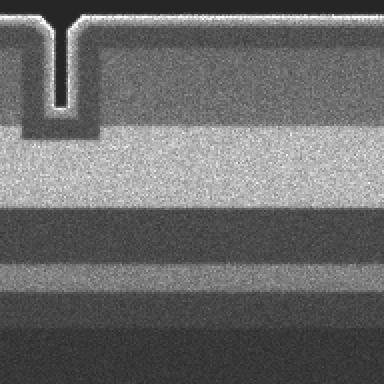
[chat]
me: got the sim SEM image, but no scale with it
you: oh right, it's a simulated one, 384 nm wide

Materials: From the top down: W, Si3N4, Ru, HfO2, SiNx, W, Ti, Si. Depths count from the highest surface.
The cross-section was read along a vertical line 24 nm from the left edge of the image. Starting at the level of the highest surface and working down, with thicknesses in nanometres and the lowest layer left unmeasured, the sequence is W 10, Si3N4 114, HfO2 68, SiNx 56, W 28, Ti 36, Si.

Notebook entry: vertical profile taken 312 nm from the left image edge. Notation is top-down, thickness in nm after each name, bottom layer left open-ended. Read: W 10, Si3N4 22, Ru 78, HfO2 82, SiNx 56, W 28, Ti 36, Si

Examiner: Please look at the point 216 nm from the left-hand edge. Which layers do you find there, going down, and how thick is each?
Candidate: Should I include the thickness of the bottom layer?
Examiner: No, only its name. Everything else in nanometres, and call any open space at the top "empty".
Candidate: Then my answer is W 10, Si3N4 22, Ru 78, HfO2 82, SiNx 56, W 28, Ti 36, Si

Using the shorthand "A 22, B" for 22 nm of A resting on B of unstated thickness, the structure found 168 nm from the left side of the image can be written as W 10, Si3N4 22, Ru 78, HfO2 82, SiNx 56, W 28, Ti 36, Si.